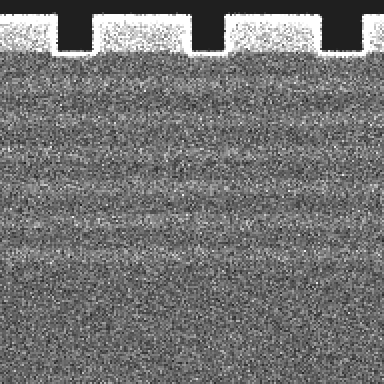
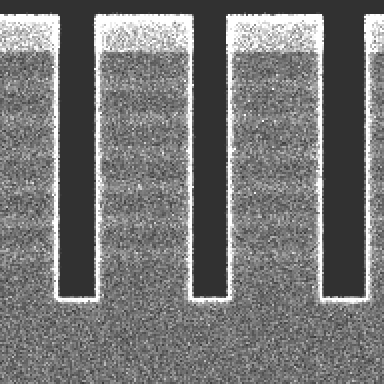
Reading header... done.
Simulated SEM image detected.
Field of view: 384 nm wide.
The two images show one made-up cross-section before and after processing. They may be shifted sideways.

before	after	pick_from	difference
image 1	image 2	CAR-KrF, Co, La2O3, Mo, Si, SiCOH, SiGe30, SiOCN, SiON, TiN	Si and SiGe30 removed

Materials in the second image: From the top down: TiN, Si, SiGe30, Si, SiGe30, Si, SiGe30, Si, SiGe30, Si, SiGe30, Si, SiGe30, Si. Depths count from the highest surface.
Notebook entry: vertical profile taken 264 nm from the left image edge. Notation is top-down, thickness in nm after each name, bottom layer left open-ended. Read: TiN 36, Si 26, SiGe30 14, Si 20, SiGe30 14, Si 20, SiGe30 14, Si 20, SiGe30 14, Si 20, SiGe30 14, Si 20, SiGe30 14, Si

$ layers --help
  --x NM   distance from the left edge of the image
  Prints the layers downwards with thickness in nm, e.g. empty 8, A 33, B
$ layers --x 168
TiN 36, Si 26, SiGe30 14, Si 20, SiGe30 14, Si 20, SiGe30 14, Si 20, SiGe30 14, Si 20, SiGe30 14, Si 20, SiGe30 14, Si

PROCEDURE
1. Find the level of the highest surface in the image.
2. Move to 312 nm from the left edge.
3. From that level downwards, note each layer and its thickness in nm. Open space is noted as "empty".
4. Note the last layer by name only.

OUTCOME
TiN 36, Si 26, SiGe30 14, Si 20, SiGe30 14, Si 20, SiGe30 14, Si 20, SiGe30 14, Si 20, SiGe30 14, Si 20, SiGe30 14, Si